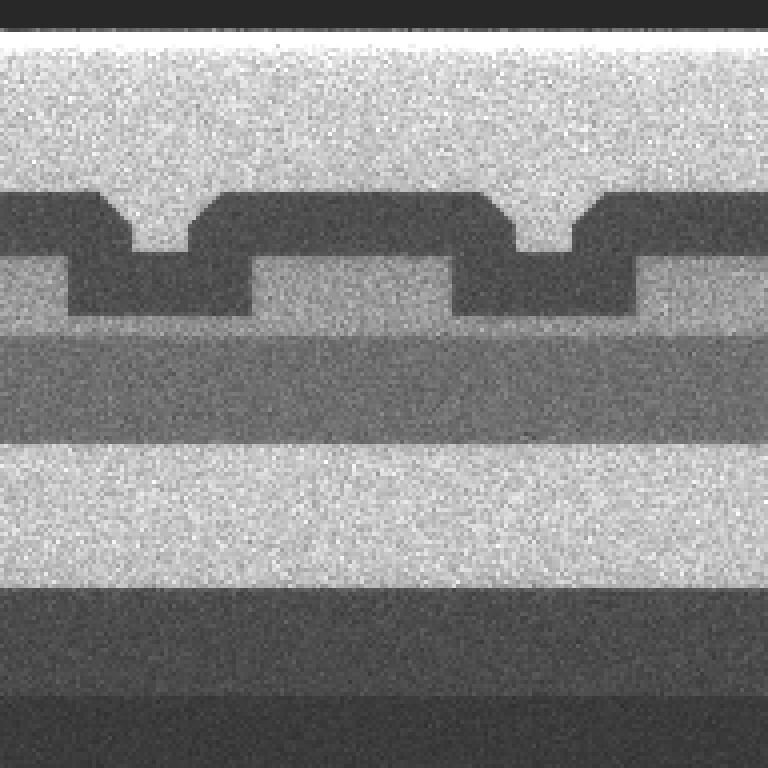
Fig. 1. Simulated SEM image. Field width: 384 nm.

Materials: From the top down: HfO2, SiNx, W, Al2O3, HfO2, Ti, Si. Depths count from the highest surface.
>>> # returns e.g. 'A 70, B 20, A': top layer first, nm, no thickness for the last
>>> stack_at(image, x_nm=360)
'HfO2 80, SiNx 32, W 40, Al2O3 54, HfO2 72, Ti 54, Si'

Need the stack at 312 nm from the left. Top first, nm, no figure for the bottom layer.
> HfO2 80, SiNx 62, W 10, Al2O3 54, HfO2 72, Ti 54, Si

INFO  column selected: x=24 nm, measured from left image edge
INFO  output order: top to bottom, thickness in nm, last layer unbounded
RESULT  HfO2 80, SiNx 32, W 40, Al2O3 54, HfO2 72, Ti 54, Si